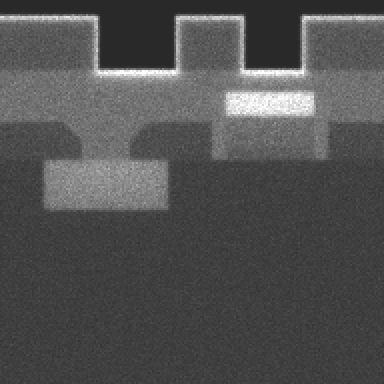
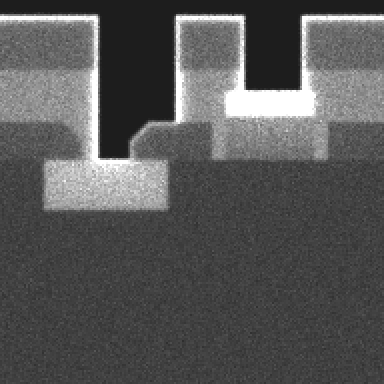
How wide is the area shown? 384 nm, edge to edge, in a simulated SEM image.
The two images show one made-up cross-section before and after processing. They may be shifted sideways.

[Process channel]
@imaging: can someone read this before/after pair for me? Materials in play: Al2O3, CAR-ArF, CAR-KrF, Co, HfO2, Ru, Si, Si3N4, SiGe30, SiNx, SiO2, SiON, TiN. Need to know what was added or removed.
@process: SiO2 removed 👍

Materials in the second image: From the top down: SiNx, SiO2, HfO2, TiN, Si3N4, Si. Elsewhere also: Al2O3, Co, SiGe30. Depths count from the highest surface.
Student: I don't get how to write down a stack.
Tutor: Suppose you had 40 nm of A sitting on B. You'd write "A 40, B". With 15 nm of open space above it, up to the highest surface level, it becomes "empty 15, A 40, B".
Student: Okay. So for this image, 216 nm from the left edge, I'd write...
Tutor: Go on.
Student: SiNx 54, SiO2 24, Al2O3 66, Si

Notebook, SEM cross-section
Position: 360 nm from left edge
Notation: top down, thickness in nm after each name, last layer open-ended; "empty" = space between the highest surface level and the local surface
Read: SiNx 54, SiO2 52, SiGe30 38, Si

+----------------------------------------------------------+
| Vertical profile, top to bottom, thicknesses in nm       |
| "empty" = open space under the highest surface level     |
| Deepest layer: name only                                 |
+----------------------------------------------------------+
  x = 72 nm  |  SiNx 54, SiO2 62, SiGe30 28, Co 50, Si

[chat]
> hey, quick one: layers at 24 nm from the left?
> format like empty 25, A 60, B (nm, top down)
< SiNx 54, SiO2 52, SiGe30 38, Si